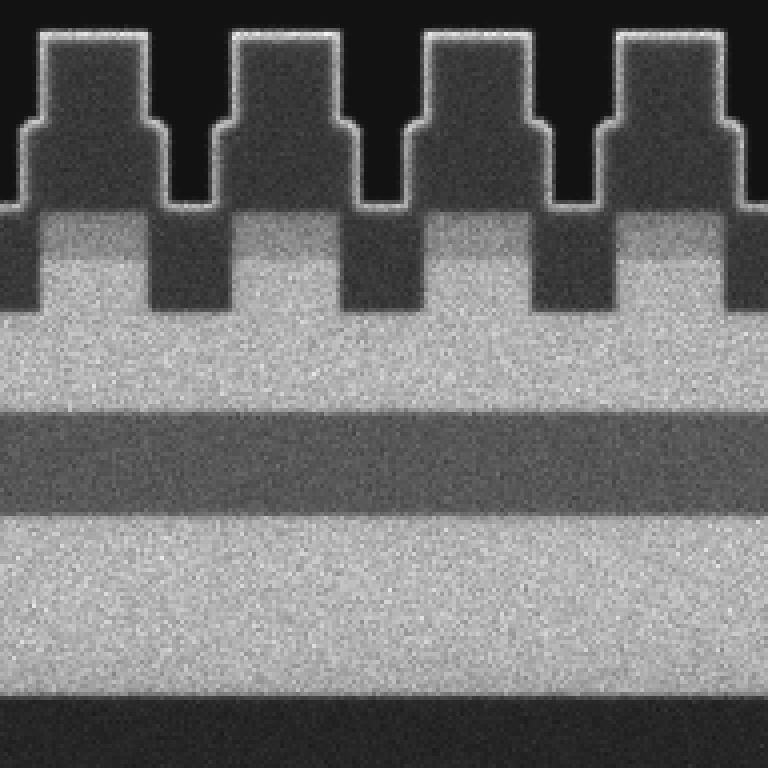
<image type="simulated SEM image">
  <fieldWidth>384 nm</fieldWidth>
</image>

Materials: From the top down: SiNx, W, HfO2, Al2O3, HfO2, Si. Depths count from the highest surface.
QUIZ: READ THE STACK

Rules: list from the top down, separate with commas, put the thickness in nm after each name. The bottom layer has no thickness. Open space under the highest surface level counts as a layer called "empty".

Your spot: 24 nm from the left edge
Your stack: SiNx 90, W 24, HfO2 76, Al2O3 52, HfO2 90, Si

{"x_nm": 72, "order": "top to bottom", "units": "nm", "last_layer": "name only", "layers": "SiNx 90, W 24, HfO2 76, Al2O3 52, HfO2 90, Si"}